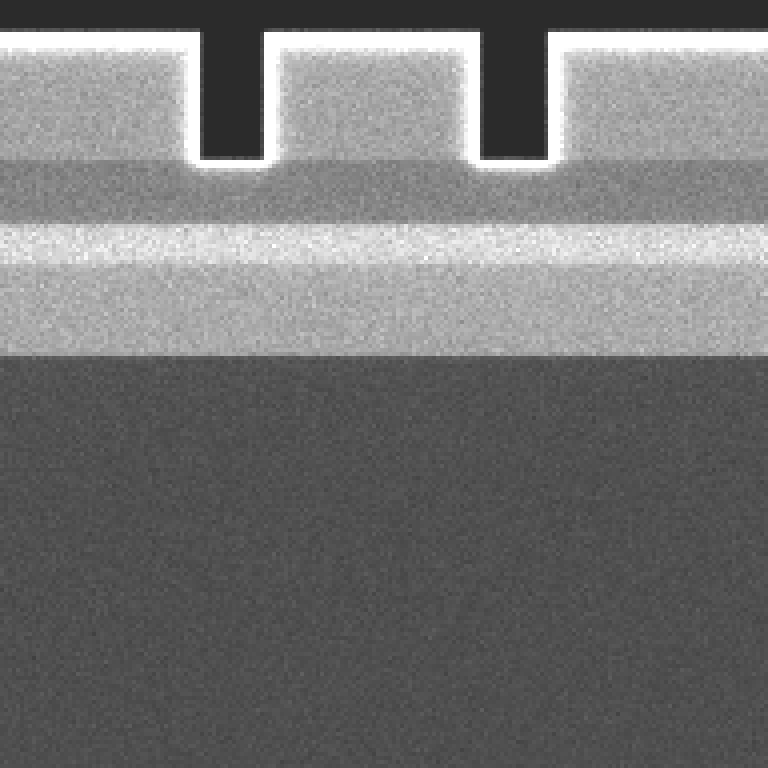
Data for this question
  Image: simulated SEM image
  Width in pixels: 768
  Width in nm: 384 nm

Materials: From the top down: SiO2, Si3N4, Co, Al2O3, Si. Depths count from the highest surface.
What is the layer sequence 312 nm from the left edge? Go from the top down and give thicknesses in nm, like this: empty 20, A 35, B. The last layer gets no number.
SiO2 64, Si3N4 32, Co 20, Al2O3 46, Si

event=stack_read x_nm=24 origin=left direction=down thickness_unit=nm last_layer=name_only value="SiO2 64, Si3N4 32, Co 20, Al2O3 46, Si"